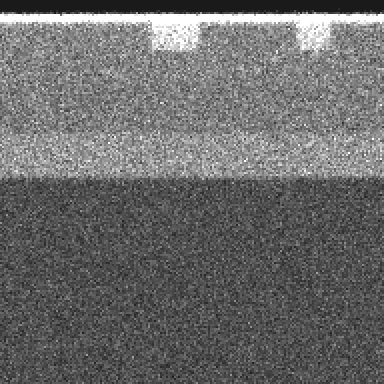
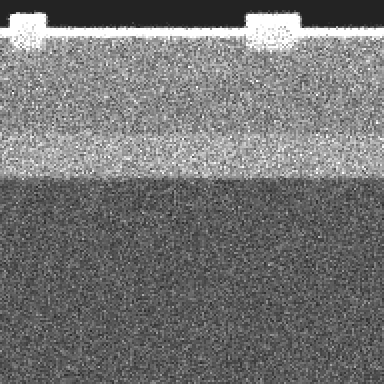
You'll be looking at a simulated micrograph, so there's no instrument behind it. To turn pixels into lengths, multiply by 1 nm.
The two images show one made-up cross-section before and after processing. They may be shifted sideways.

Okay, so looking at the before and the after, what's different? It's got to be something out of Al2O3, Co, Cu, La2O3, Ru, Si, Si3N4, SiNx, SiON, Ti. SiNx, removed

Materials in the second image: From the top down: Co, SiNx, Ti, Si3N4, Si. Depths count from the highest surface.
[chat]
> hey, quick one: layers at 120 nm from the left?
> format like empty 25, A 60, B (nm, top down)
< empty 14, SiNx 52, Ti 52, Si3N4 44, Si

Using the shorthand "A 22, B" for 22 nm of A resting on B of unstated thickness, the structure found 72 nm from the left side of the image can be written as empty 14, SiNx 52, Ti 52, Si3N4 44, Si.